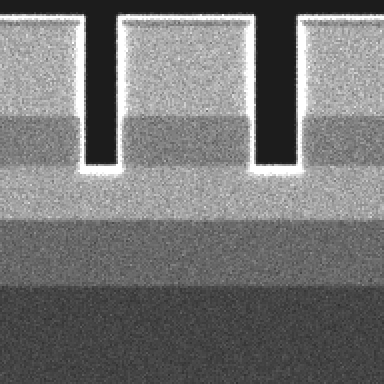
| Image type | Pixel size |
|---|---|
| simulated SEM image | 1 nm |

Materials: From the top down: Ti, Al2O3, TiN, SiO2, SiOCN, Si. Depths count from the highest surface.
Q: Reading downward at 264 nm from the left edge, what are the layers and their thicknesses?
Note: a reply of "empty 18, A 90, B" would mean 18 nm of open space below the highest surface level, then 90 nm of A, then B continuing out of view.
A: empty 150, SiO2 54, SiOCN 66, Si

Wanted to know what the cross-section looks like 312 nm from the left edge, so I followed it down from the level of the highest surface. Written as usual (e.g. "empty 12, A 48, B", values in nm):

Ti 10, Al2O3 90, TiN 50, SiO2 54, SiOCN 66, Si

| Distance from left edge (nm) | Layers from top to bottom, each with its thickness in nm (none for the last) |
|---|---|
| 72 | Ti 10, Al2O3 90, TiN 50, SiO2 54, SiOCN 66, Si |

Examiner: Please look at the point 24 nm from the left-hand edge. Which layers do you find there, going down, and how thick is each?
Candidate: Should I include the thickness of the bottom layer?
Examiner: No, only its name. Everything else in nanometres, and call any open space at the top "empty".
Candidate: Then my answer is Ti 10, Al2O3 90, TiN 50, SiO2 54, SiOCN 66, Si